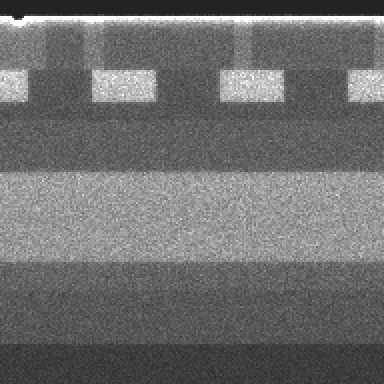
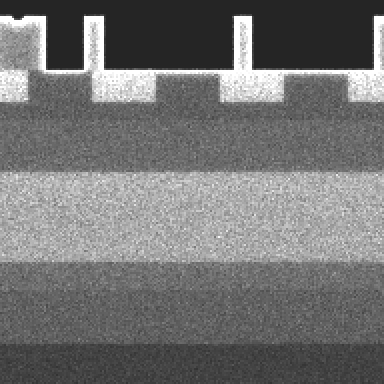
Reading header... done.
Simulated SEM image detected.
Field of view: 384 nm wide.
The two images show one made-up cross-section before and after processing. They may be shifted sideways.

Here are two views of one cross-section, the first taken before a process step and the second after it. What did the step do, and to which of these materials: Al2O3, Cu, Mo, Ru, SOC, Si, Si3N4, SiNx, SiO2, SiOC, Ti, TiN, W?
It removed SOC.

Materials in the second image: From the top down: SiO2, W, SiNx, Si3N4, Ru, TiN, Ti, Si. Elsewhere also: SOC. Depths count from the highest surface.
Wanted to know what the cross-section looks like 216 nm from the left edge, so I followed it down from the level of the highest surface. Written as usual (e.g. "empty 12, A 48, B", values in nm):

empty 54, SiNx 50, Si3N4 52, Ru 90, TiN 28, Ti 54, Si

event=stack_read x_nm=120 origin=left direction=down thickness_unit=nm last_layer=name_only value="empty 54, W 32, SiNx 18, Si3N4 52, Ru 90, TiN 28, Ti 54, Si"